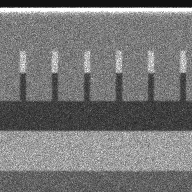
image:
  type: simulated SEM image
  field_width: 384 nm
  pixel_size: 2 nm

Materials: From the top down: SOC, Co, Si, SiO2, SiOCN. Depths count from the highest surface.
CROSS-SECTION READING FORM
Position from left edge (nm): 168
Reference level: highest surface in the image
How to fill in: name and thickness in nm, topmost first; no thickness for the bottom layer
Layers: SOC 86, Co 44, Si 116, SiO2 80, SiOCN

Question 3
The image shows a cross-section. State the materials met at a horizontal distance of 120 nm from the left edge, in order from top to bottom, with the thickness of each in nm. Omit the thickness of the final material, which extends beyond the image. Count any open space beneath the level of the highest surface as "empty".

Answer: SOC 186, Si 60, SiO2 80, SiOCN